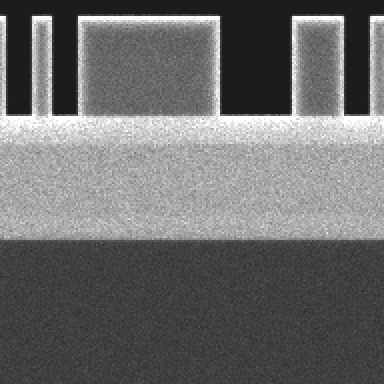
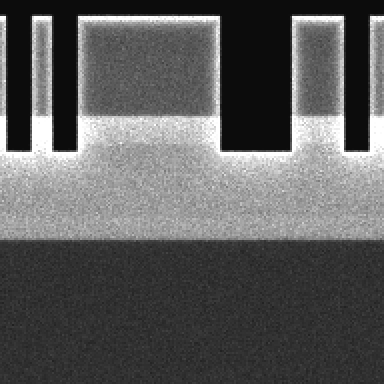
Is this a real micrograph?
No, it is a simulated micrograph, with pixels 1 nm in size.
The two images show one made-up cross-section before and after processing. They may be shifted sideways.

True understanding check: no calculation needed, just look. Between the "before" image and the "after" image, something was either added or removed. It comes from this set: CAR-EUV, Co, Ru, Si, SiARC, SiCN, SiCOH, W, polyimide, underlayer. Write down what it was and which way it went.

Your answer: Co and W (removed)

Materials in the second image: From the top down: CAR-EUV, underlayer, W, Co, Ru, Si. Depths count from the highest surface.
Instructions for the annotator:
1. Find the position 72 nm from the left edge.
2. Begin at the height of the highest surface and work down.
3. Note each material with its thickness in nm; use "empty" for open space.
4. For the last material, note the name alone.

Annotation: empty 136, Co 64, Ru 24, Si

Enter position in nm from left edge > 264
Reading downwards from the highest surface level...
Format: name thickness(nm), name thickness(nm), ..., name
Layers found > empty 136, Co 64, Ru 24, Si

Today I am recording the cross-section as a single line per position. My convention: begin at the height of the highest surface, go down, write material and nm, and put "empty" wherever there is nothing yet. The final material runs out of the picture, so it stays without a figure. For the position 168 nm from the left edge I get CAR-EUV 40, underlayer 60, W 28, Co 72, Ru 24, Si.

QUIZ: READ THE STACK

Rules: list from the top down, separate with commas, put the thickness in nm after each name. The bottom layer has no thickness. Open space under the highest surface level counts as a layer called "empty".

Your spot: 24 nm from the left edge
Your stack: empty 136, Co 64, Ru 24, Si